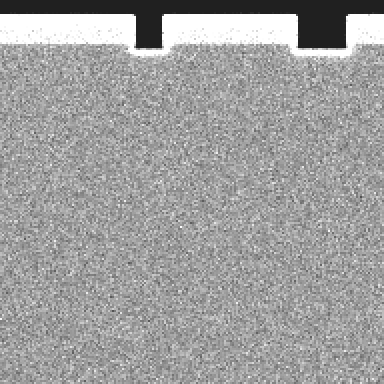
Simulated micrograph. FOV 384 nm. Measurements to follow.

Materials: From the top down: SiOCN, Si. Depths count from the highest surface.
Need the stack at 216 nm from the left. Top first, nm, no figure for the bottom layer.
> SiOCN 28, Si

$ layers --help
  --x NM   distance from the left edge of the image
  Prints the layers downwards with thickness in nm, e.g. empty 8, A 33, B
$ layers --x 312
empty 34, Si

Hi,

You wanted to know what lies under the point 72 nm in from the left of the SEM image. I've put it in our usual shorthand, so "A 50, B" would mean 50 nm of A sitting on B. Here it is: SiOCN 28, Si